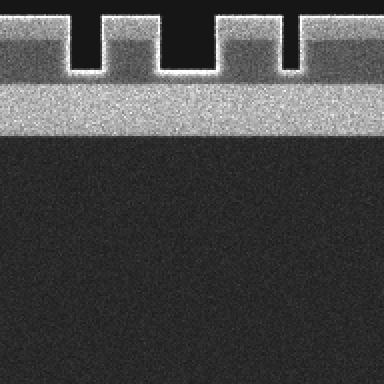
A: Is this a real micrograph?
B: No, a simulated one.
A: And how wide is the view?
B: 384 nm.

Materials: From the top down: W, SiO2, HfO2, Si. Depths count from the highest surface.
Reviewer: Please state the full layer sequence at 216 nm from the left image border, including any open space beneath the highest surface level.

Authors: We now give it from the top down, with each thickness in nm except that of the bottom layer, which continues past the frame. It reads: W 24, SiO2 44, HfO2 52, Si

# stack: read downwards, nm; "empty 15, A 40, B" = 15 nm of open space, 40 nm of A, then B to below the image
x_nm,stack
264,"W 24, SiO2 44, HfO2 52, Si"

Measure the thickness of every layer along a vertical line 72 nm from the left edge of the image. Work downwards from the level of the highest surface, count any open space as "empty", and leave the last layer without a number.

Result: empty 54, SiO2 14, HfO2 52, Si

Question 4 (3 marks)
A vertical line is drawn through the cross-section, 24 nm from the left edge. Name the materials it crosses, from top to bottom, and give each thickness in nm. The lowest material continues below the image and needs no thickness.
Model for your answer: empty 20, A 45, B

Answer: W 24, SiO2 44, HfO2 52, Si